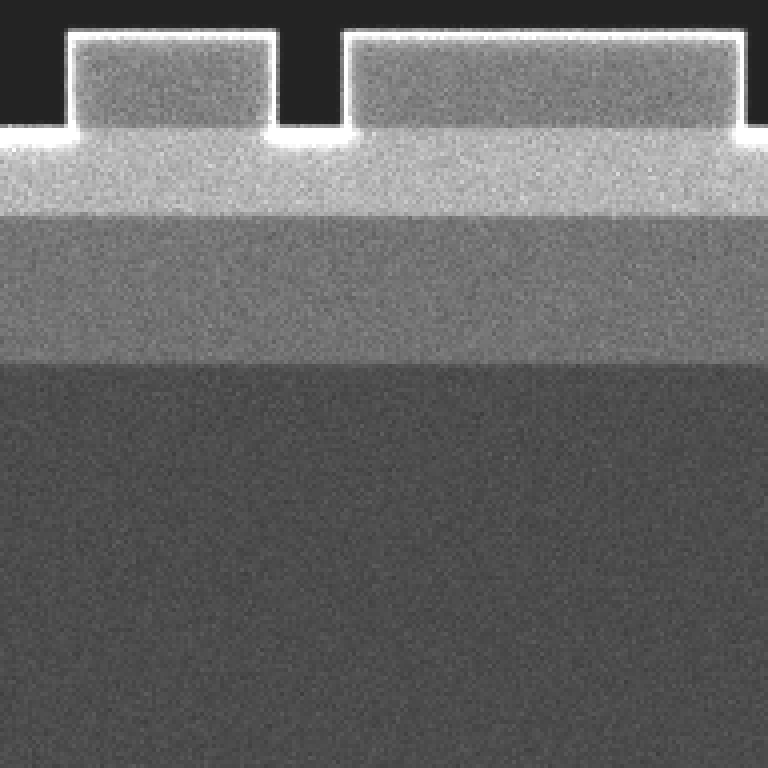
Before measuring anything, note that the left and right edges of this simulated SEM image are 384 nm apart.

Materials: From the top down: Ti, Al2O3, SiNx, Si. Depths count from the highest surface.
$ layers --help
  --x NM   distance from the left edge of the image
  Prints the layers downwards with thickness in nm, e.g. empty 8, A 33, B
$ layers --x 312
Ti 48, Al2O3 44, SiNx 74, Si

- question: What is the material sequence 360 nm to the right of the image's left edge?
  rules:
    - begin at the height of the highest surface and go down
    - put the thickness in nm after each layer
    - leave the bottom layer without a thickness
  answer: Ti 48, Al2O3 44, SiNx 74, Si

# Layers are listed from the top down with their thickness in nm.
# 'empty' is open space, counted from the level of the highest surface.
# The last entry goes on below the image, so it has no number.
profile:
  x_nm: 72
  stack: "Ti 48, Al2O3 44, SiNx 74, Si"